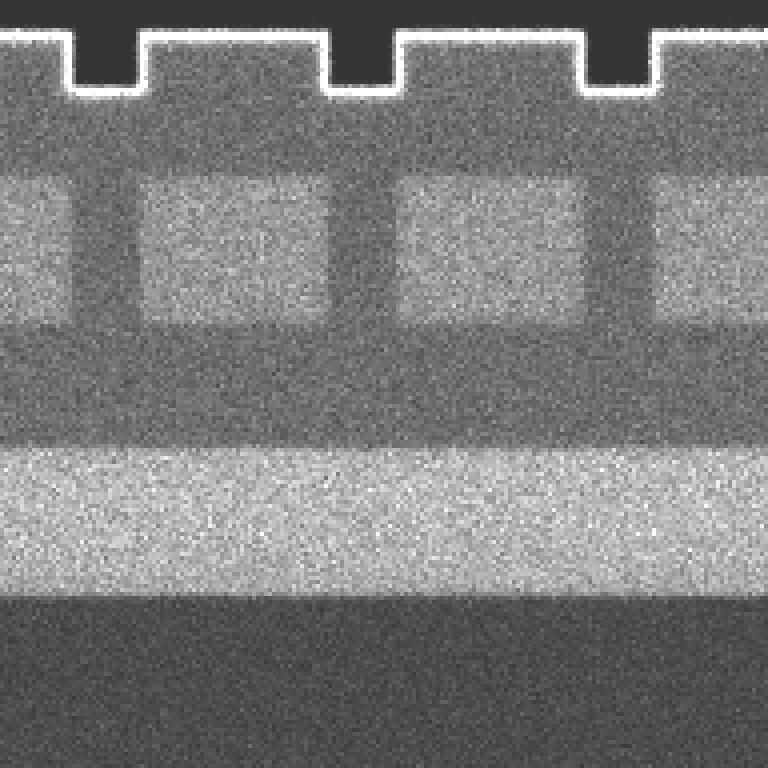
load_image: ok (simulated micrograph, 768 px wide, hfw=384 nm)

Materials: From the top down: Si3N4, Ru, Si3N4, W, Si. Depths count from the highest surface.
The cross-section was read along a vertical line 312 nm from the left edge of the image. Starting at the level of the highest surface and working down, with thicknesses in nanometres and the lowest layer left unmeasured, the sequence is empty 28, Si3N4 180, W 74, Si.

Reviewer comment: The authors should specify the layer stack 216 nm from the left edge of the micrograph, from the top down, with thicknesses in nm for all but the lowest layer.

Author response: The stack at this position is Si3N4 72, Ru 74, Si3N4 62, W 74, Si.